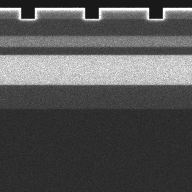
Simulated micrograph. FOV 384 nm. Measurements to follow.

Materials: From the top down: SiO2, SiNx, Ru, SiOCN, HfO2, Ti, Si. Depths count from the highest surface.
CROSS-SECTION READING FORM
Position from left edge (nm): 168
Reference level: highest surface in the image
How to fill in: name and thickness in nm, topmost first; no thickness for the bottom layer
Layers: SiO2 22, SiNx 34, Ru 22, SiOCN 16, HfO2 60, Ti 48, Si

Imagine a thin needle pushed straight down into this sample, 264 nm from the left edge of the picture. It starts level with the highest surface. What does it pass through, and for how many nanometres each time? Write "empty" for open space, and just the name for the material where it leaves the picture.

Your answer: SiO2 22, SiNx 34, Ru 22, SiOCN 16, HfO2 60, Ti 48, Si